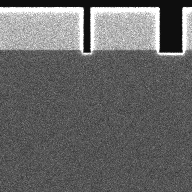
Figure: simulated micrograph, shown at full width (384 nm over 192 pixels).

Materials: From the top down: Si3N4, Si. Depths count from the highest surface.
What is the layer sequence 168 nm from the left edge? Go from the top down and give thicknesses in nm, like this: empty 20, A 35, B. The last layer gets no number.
empty 90, Si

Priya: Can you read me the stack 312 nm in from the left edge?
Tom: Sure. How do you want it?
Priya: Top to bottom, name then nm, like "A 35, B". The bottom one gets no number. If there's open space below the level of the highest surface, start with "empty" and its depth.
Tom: Si3N4 84, Si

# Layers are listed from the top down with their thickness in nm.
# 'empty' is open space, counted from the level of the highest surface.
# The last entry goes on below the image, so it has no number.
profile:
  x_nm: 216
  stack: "Si3N4 84, Si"